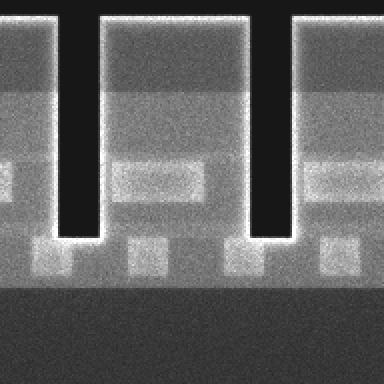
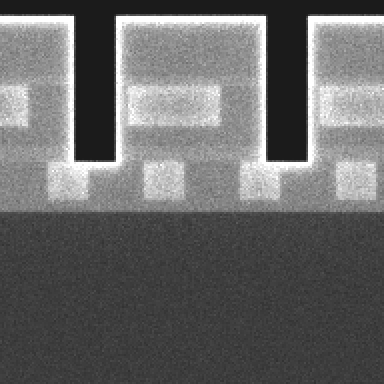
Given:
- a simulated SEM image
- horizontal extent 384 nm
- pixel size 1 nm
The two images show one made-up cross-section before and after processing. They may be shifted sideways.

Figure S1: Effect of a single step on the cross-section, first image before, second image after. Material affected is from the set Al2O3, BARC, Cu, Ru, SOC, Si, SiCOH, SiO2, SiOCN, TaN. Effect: removed SOC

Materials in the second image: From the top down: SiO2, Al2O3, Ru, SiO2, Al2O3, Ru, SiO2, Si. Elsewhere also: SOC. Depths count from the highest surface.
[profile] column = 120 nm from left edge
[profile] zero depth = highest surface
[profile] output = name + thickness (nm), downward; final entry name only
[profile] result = SiO2 60, Al2O3 10, SiO2 60, Al2O3 16, SiO2 50, Si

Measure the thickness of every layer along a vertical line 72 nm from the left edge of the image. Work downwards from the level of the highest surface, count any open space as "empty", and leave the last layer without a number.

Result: SiO2 60, Al2O3 10, SiO2 60, Al2O3 16, Ru 38, SiO2 12, Si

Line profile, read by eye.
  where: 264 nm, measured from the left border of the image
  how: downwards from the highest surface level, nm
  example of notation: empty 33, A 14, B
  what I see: SiO2 60, Al2O3 10, SiO2 60, Al2O3 16, Ru 38, SiO2 12, Si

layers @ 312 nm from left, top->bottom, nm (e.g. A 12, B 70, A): SiO2 60, Al2O3 10, SiO2 60, Al2O3 16, SiO2 50, Si